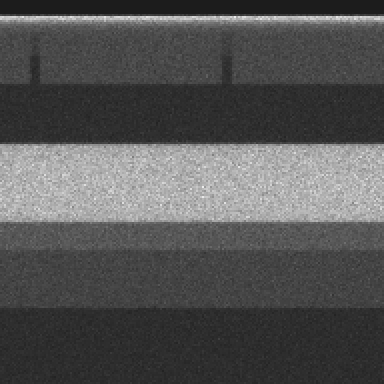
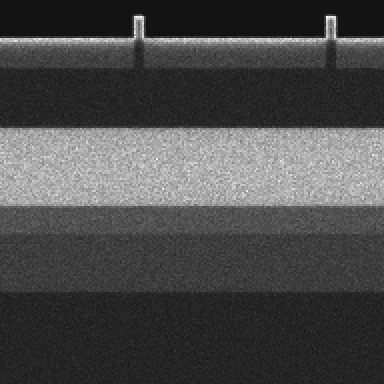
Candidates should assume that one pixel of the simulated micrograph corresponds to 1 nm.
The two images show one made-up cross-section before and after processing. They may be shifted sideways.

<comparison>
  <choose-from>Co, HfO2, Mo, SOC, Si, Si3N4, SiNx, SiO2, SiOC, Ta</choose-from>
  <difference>SOC removed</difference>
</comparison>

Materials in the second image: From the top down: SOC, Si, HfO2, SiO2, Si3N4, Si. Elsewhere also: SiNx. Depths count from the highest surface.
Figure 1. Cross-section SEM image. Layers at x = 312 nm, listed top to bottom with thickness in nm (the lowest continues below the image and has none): empty 22, SOC 30, Si 60, HfO2 78, SiO2 28, Si3N4 58, Si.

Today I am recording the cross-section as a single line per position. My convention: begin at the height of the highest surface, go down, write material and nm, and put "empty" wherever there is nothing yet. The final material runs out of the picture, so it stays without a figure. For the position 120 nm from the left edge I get empty 22, SOC 30, Si 60, HfO2 78, SiO2 28, Si3N4 58, Si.